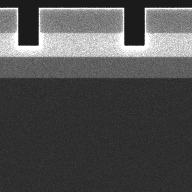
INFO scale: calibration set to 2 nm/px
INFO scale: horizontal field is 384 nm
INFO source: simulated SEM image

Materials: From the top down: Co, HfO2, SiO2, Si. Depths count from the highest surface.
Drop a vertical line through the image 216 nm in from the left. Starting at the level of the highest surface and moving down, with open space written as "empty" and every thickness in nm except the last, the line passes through Co 50, HfO2 48, SiO2 42, Si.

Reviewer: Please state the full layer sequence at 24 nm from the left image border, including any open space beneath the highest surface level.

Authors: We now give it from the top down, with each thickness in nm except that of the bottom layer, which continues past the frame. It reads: Co 50, HfO2 48, SiO2 42, Si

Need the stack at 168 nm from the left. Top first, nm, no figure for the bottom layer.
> Co 50, HfO2 48, SiO2 42, Si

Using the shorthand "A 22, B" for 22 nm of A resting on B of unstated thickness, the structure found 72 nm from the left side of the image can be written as empty 76, HfO2 22, SiO2 42, Si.